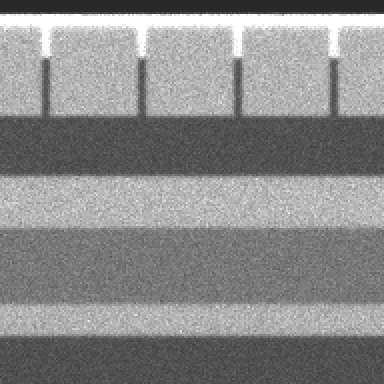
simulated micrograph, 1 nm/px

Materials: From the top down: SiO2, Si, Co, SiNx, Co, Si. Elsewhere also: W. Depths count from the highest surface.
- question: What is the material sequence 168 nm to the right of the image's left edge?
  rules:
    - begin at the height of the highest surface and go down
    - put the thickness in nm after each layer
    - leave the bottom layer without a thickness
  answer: SiO2 100, Si 60, Co 52, SiNx 76, Co 32, Si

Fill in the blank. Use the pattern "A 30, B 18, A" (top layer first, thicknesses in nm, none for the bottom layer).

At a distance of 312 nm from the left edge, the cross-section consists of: SiO2 100, Si 60, Co 52, SiNx 76, Co 32, Si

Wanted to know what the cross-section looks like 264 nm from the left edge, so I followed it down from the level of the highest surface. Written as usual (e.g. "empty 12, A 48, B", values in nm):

SiO2 100, Si 60, Co 52, SiNx 76, Co 32, Si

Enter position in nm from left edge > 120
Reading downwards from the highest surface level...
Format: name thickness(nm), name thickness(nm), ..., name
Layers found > SiO2 100, Si 60, Co 52, SiNx 76, Co 32, Si